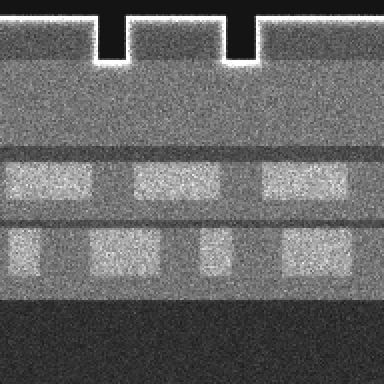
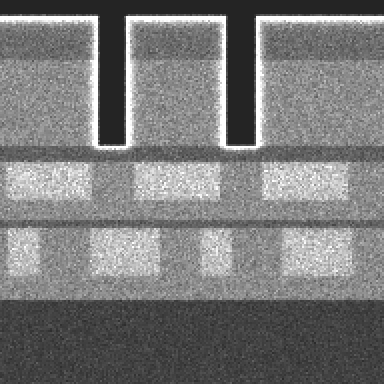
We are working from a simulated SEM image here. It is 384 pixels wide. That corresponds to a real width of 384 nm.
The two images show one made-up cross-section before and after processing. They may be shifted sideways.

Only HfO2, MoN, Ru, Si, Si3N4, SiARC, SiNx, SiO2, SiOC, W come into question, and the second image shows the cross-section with SiO2 removed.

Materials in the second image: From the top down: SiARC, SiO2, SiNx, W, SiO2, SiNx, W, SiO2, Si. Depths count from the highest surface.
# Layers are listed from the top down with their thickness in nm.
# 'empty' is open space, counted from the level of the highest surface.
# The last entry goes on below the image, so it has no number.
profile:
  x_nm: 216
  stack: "SiARC 44, SiO2 86, SiNx 16, W 38, SiO2 20, SiNx 8, W 48, SiO2 24, Si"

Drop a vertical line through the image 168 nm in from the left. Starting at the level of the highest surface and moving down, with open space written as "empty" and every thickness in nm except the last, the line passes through SiARC 44, SiO2 86, SiNx 16, W 38, SiO2 20, SiNx 8, SiO2 72, Si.